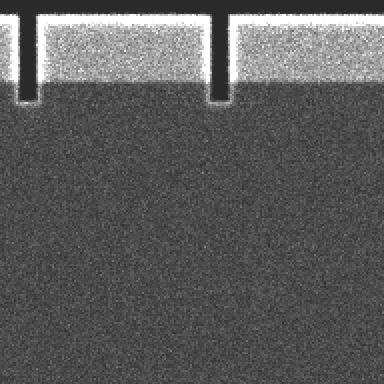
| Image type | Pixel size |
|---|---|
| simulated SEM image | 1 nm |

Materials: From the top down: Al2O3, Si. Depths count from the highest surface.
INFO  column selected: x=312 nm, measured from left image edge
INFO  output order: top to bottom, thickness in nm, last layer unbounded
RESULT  Al2O3 66, Si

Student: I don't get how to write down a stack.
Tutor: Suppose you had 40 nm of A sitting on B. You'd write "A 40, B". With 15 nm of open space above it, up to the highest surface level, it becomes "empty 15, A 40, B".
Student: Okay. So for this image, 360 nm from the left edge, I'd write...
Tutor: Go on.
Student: Al2O3 66, Si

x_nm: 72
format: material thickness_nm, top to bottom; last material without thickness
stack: Al2O3 66, Si